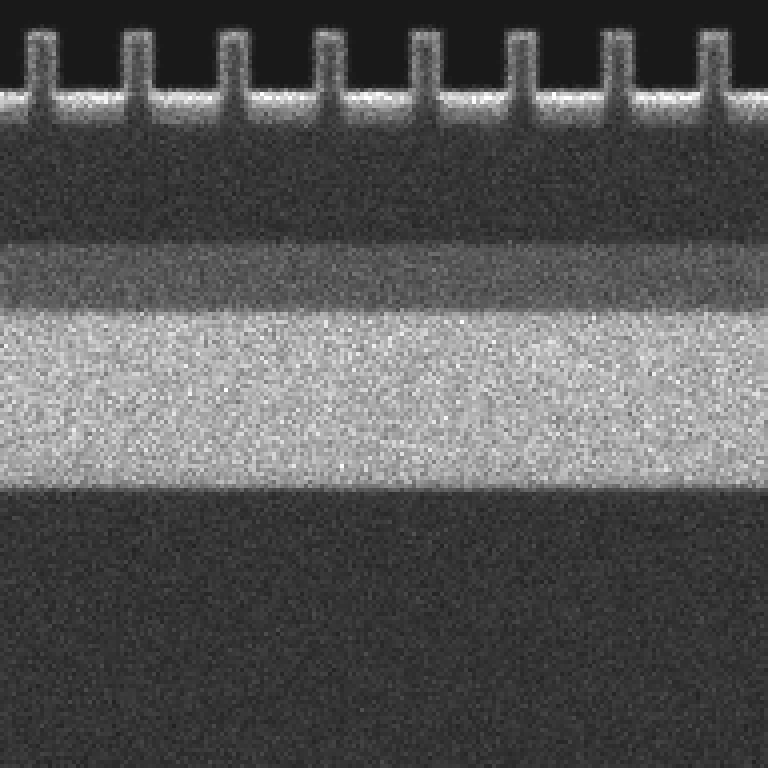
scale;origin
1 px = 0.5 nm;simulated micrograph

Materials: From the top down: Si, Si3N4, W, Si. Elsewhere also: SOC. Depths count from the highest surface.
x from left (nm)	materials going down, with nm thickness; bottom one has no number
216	Si 106, Si3N4 34, W 88, Si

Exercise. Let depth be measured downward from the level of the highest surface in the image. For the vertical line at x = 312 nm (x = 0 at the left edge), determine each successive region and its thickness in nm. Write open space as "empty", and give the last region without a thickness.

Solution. Si 106, Si3N4 34, W 88, Si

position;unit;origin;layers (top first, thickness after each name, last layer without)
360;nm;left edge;Si 106, Si3N4 34, W 88, Si